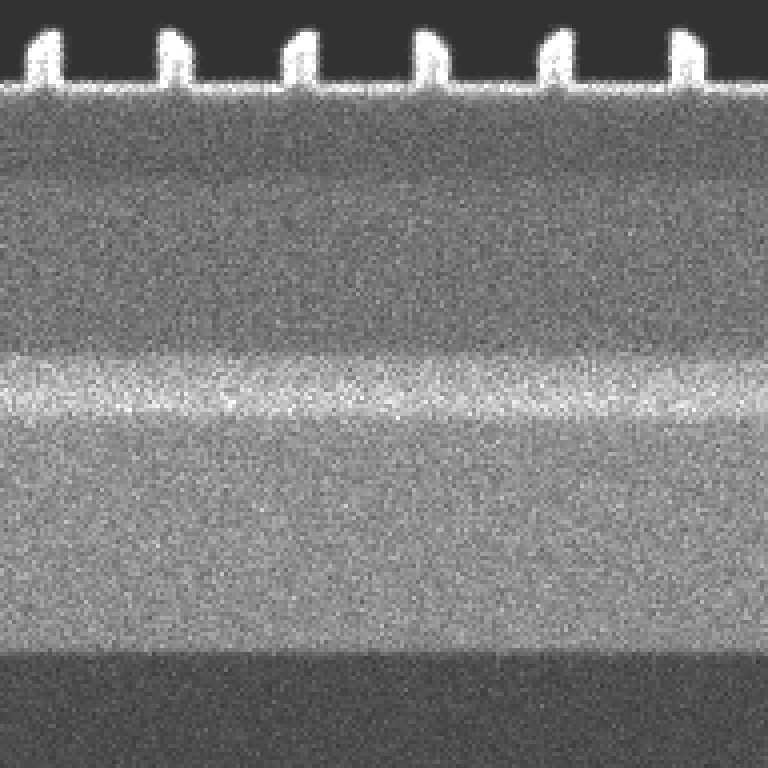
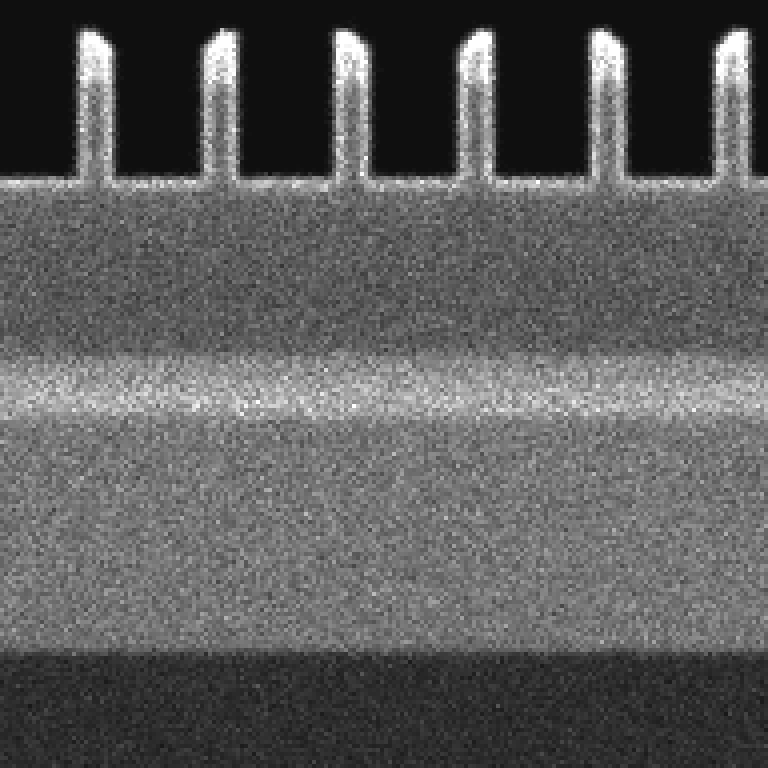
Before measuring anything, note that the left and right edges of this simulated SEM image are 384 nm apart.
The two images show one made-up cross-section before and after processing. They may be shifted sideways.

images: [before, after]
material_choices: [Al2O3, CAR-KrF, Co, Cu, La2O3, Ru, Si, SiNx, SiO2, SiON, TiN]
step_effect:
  removed: SiNx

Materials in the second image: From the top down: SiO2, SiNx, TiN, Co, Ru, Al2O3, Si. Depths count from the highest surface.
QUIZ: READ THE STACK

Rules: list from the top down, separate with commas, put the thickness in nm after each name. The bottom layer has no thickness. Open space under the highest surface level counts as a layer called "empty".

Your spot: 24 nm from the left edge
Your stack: empty 74, TiN 88, Co 14, Ru 16, Al2O3 118, Si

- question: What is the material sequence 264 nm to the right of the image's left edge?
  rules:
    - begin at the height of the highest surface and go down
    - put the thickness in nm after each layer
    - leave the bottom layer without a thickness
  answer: empty 74, TiN 88, Co 14, Ru 16, Al2O3 118, Si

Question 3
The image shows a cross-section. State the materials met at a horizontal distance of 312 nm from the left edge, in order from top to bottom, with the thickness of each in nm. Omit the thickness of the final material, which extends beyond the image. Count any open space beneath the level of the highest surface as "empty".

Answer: empty 74, TiN 88, Co 14, Ru 16, Al2O3 118, Si